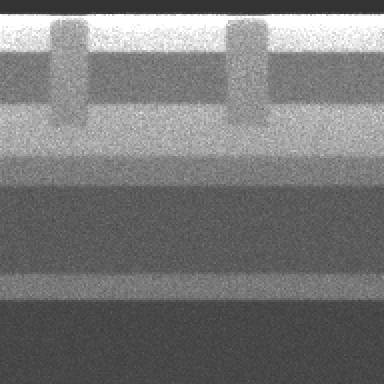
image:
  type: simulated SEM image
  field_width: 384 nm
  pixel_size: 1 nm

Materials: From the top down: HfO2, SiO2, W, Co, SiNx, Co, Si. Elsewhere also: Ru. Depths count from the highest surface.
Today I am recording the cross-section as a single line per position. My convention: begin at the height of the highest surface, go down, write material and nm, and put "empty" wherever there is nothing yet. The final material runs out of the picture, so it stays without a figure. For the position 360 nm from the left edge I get HfO2 36, SiO2 52, W 52, Co 30, SiNx 88, Co 26, Si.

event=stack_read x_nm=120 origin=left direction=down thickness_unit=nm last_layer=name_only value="HfO2 36, SiO2 52, W 52, Co 30, SiNx 88, Co 26, Si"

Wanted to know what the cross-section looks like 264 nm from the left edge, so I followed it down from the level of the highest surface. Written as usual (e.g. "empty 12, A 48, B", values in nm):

Ru 110, W 30, Co 30, SiNx 88, Co 26, Si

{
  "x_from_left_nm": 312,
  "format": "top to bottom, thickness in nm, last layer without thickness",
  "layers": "HfO2 36, SiO2 52, W 52, Co 30, SiNx 88, Co 26, Si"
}